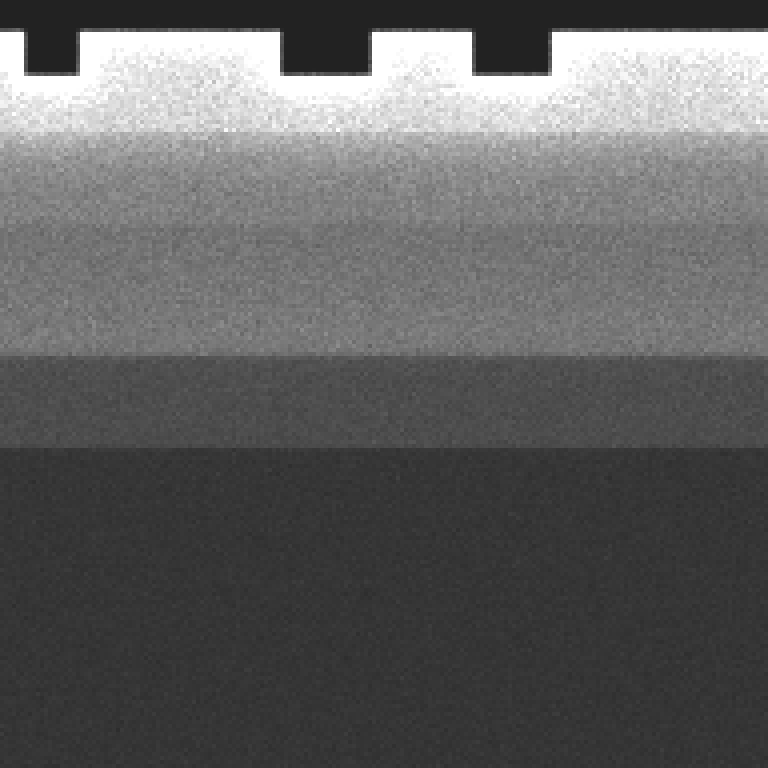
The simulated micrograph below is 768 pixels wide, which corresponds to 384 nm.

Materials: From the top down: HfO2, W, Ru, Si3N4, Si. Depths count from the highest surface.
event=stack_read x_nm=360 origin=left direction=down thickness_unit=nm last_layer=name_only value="HfO2 50, W 46, Ru 66, Si3N4 46, Si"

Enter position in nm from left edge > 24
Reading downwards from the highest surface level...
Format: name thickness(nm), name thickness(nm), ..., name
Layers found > empty 22, HfO2 28, W 46, Ru 66, Si3N4 46, Si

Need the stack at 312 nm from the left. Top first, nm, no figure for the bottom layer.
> HfO2 50, W 46, Ru 66, Si3N4 46, Si